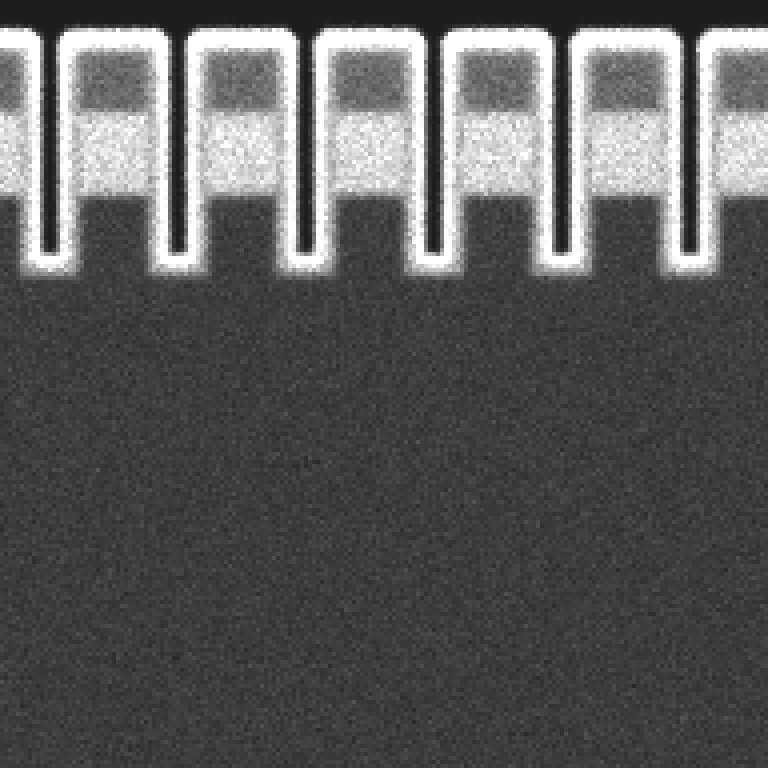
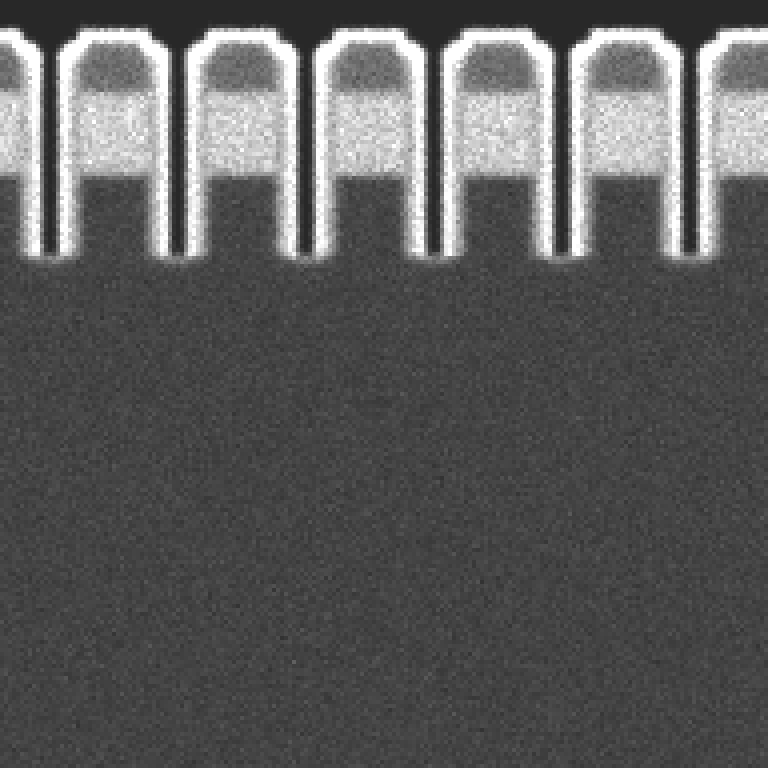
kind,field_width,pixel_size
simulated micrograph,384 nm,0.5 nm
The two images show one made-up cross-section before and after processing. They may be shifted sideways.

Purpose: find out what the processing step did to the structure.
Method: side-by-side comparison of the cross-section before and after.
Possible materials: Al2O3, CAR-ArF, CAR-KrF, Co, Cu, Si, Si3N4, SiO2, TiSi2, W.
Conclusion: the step removed Al2O3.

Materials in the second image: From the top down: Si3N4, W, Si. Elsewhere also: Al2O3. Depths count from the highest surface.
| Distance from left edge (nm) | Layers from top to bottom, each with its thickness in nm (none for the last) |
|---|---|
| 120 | Si3N4 30, W 42, Si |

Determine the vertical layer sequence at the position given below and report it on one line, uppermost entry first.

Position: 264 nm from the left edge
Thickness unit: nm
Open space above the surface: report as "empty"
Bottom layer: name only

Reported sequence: Si3N4 30, W 42, Si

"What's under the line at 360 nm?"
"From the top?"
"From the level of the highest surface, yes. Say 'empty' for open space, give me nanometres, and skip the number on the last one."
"Si3N4 30, W 42, Si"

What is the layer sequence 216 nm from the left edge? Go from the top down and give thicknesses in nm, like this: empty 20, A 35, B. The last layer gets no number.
empty 112, Si